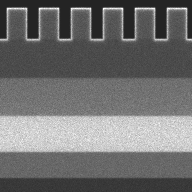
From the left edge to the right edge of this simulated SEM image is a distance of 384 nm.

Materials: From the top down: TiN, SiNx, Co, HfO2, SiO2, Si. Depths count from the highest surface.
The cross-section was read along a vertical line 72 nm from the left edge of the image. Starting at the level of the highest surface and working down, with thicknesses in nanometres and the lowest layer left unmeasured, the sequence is empty 62, SiNx 78, Co 76, HfO2 72, SiO2 52, Si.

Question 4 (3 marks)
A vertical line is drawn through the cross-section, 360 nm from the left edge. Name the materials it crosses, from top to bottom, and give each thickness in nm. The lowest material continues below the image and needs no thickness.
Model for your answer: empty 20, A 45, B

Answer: TiN 62, SiNx 78, Co 76, HfO2 72, SiO2 52, Si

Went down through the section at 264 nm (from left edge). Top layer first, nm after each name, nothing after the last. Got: empty 62, SiNx 78, Co 76, HfO2 72, SiO2 52, Si